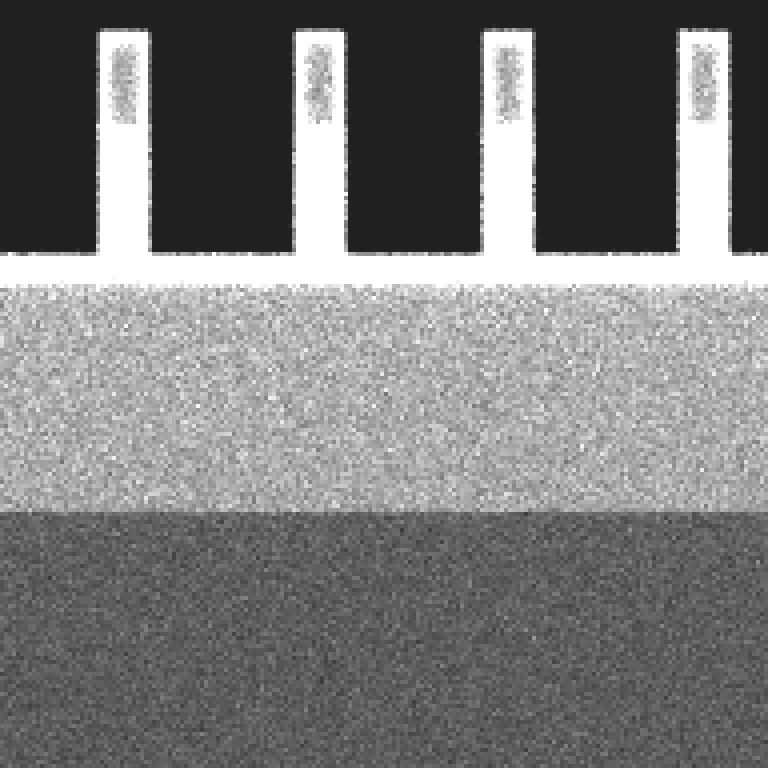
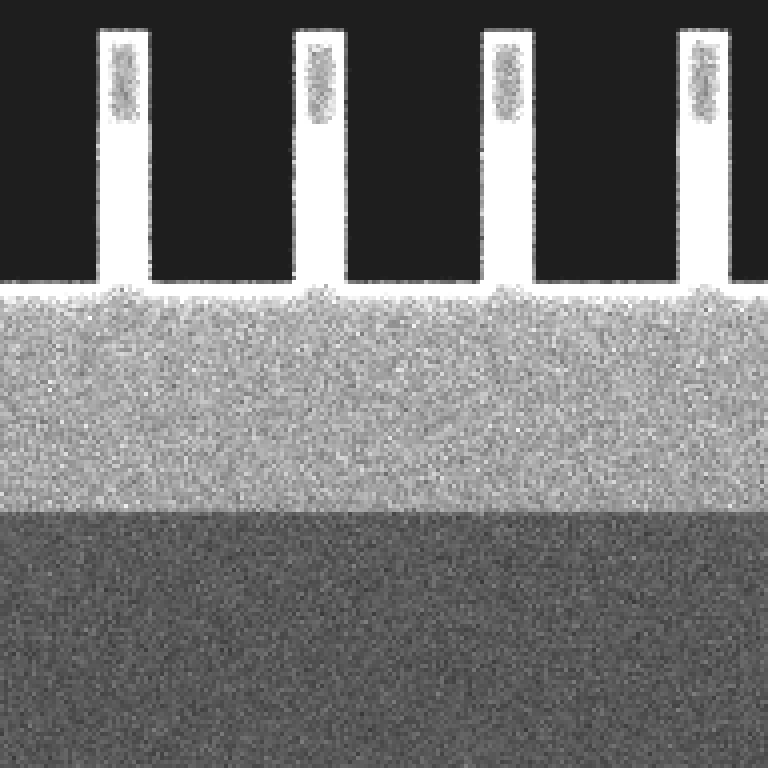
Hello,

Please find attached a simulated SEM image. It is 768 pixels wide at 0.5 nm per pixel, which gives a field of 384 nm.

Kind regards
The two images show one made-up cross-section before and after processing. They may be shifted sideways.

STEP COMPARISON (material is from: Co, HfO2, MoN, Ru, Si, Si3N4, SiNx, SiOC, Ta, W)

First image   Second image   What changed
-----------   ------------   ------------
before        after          Co, removed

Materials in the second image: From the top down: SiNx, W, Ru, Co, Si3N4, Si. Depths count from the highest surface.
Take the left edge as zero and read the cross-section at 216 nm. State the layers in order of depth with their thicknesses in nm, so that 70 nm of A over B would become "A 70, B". empty 126, Si3N4 114, Si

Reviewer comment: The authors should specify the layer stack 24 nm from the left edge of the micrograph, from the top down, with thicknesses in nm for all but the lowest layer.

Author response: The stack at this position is empty 126, Si3N4 114, Si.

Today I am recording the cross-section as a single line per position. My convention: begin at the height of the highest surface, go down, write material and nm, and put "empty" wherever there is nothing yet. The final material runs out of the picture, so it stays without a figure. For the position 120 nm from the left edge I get empty 126, Si3N4 114, Si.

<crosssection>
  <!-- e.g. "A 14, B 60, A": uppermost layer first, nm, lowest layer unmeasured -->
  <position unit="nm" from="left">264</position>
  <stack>SiNx 46, W 52, Ru 14, Co 14, Si3N4 114, Si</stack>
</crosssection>